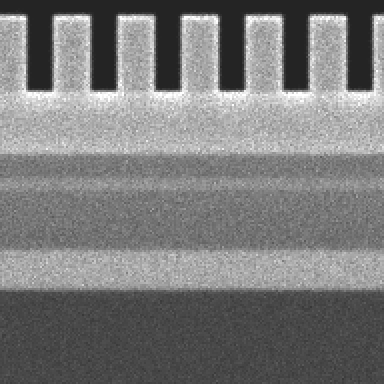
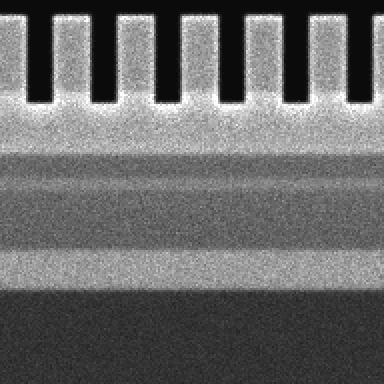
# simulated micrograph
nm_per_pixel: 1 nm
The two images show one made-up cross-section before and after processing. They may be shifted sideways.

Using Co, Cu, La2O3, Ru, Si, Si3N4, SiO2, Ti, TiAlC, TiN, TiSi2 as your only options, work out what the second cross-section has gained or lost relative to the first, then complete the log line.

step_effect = removed Ru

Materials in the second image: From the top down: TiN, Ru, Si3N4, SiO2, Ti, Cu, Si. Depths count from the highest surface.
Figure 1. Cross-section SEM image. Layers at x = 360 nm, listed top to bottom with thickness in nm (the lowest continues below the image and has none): empty 88, Ru 50, Si3N4 24, SiO2 12, Ti 60, Cu 40, Si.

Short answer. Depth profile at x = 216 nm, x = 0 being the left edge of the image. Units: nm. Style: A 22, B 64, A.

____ TiN 76, Ru 62, Si3N4 24, SiO2 12, Ti 60, Cu 40, Si